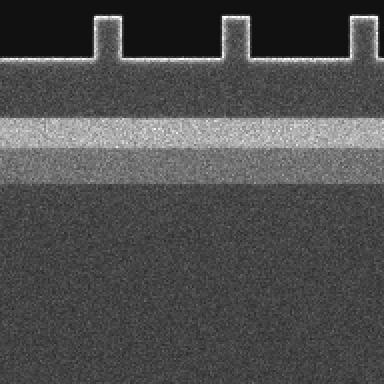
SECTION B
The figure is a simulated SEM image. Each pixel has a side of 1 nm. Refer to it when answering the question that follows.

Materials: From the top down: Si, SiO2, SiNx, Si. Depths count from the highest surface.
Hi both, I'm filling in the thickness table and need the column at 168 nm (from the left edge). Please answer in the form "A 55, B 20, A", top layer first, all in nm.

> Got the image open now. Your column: empty 42, Si 60, SiO2 30, SiNx 36, Si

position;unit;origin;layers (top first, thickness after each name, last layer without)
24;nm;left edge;empty 42, Si 60, SiO2 30, SiNx 36, Si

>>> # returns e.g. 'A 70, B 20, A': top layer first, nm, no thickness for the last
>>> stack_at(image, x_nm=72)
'empty 42, Si 60, SiO2 30, SiNx 36, Si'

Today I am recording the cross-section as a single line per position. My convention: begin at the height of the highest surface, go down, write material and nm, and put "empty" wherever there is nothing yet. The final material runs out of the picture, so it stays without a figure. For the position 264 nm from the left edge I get empty 42, Si 60, SiO2 30, SiNx 36, Si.